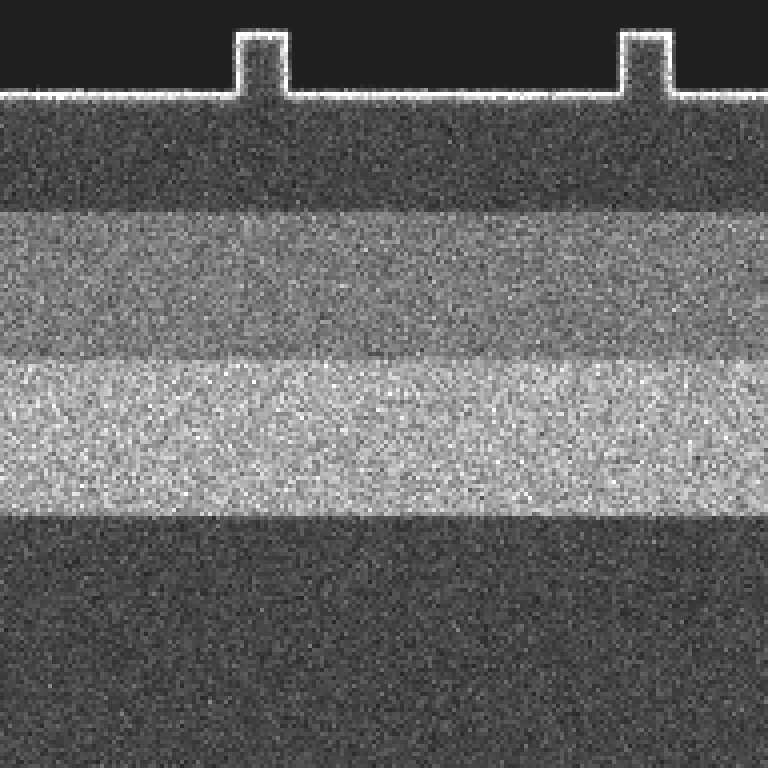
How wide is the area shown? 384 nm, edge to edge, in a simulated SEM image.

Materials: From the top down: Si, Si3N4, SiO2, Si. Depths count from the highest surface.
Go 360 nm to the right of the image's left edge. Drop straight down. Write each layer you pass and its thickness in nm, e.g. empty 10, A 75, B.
empty 30, Si 60, Si3N4 74, SiO2 78, Si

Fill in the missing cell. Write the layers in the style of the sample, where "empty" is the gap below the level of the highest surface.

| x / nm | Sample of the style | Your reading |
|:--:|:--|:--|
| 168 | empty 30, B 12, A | empty 30, Si 60, Si3N4 74, SiO2 78, Si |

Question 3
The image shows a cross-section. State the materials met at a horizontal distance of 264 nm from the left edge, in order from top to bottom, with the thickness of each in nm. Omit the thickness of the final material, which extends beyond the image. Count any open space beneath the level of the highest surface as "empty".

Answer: empty 30, Si 60, Si3N4 74, SiO2 78, Si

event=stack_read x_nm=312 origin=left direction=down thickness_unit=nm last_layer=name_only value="Si 90, Si3N4 74, SiO2 78, Si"